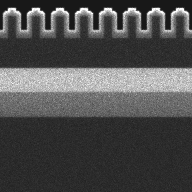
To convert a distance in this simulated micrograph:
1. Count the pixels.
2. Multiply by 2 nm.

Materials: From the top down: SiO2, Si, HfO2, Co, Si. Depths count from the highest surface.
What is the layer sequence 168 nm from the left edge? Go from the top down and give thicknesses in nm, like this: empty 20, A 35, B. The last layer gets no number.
SiO2 16, Si 104, HfO2 48, Co 50, Si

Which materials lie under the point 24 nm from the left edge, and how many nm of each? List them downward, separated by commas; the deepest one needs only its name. SiO2 16, Si 104, HfO2 48, Co 50, Si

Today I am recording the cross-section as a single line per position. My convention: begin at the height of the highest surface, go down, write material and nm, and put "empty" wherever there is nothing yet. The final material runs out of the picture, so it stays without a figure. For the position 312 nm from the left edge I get SiO2 16, Si 104, HfO2 48, Co 50, Si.